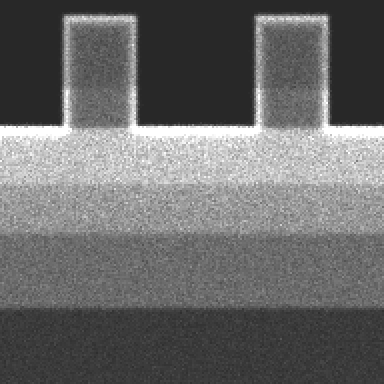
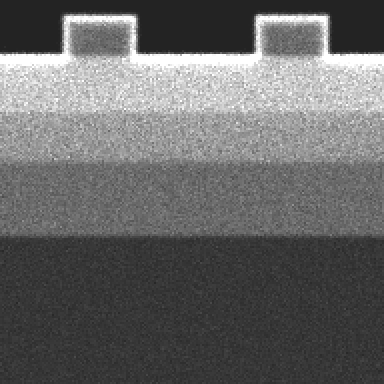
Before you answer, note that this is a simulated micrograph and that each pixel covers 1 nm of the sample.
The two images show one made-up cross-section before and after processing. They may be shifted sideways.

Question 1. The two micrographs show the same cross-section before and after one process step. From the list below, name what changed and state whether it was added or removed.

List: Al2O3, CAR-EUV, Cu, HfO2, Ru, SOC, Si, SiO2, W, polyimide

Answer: SOC, removed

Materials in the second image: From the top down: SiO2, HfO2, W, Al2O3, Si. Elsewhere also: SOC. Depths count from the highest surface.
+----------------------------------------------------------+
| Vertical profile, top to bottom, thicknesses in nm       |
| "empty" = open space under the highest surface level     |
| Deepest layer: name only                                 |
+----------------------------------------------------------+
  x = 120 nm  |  SiO2 40, HfO2 56, W 50, Al2O3 74, Si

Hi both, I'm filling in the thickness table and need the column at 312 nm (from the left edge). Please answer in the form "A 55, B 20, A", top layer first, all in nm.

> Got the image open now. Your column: SiO2 40, HfO2 56, W 50, Al2O3 74, Si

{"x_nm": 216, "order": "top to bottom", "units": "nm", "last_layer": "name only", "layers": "empty 40, HfO2 56, W 50, Al2O3 74, Si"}